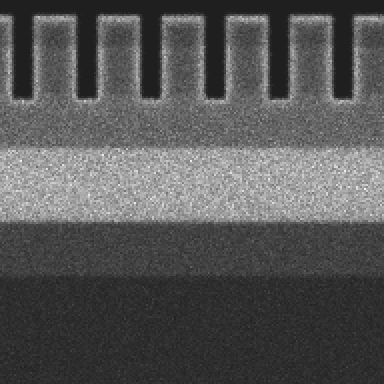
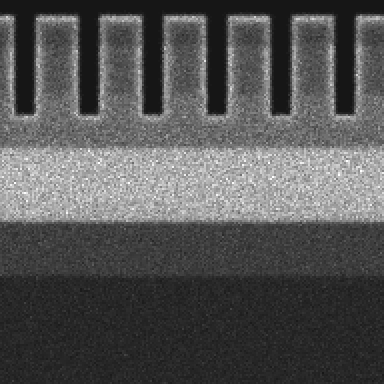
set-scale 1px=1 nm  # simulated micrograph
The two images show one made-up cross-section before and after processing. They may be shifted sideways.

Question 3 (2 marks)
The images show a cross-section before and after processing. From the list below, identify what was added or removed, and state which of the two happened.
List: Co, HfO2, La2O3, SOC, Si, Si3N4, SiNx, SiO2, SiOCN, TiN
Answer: Co was removed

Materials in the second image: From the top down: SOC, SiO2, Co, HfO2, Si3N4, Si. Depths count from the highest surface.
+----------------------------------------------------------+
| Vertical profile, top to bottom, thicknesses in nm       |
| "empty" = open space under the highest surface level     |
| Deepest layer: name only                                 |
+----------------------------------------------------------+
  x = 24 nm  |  empty 100, Co 32, HfO2 74, Si3N4 54, Si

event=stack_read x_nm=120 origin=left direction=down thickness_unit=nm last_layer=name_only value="SOC 30, SiO2 48, Co 54, HfO2 74, Si3N4 54, Si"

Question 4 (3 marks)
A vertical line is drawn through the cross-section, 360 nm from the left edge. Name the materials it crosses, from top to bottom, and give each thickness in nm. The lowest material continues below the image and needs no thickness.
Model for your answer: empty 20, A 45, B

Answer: SOC 30, SiO2 48, Co 54, HfO2 74, Si3N4 54, Si